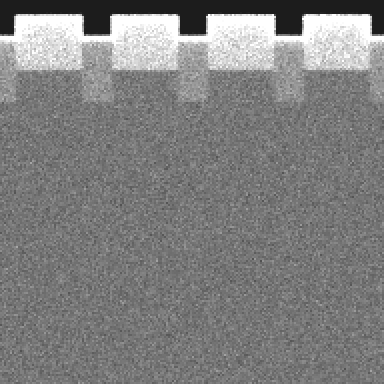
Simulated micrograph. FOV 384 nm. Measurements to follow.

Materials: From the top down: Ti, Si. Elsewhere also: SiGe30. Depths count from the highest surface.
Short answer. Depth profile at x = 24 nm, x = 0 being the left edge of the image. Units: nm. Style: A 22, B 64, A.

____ Ti 54, Si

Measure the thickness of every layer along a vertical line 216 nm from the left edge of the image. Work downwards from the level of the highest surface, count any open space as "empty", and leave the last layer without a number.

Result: Ti 54, Si